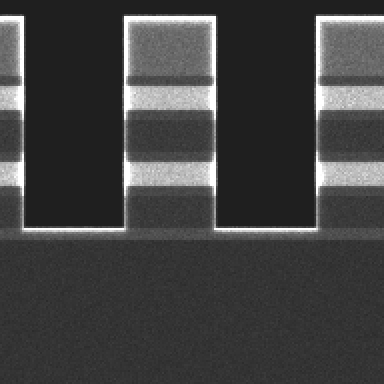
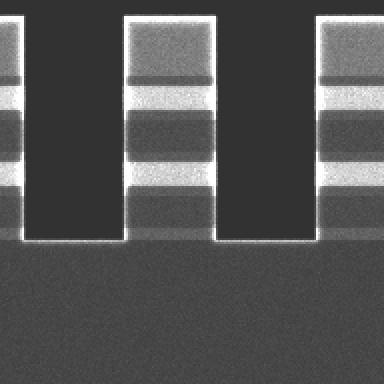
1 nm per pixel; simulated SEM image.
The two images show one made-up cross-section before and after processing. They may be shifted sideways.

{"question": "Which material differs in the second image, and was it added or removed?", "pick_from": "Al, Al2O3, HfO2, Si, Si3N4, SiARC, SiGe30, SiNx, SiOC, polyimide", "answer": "Si3N4, removed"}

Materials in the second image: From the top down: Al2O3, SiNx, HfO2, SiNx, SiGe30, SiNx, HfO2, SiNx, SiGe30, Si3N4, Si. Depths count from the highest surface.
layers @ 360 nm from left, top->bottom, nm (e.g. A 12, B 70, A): Al2O3 60, SiNx 10, HfO2 24, SiNx 10, SiGe30 32, SiNx 10, HfO2 24, SiNx 10, SiGe30 32, Si3N4 12, Si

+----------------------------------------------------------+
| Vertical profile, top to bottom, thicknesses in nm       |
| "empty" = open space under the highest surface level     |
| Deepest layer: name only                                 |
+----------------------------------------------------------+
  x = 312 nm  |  empty 224, Si